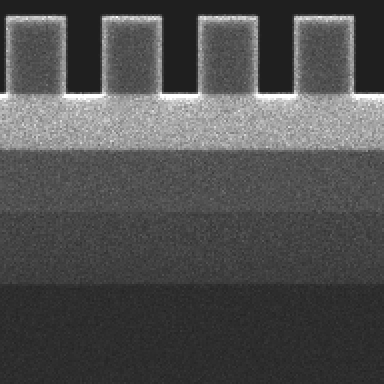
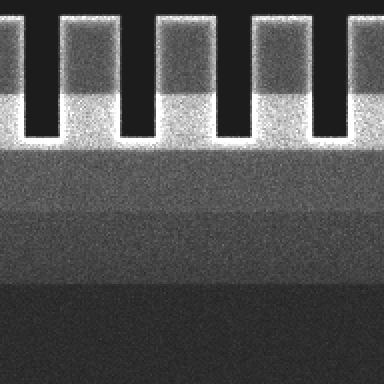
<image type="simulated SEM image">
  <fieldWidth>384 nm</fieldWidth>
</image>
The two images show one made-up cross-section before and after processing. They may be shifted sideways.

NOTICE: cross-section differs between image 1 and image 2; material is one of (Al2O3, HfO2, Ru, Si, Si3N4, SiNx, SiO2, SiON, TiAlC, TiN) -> removed: HfO2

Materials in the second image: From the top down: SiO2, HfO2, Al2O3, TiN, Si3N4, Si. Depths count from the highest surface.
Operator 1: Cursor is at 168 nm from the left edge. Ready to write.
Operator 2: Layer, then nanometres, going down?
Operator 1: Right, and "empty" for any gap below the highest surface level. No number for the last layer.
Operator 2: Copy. SiO2 78, HfO2 56, Al2O3 62, TiN 52, Si3N4 20, Si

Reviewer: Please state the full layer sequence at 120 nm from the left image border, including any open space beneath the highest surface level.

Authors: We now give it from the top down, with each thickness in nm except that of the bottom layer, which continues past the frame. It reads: empty 122, HfO2 12, Al2O3 62, TiN 52, Si3N4 20, Si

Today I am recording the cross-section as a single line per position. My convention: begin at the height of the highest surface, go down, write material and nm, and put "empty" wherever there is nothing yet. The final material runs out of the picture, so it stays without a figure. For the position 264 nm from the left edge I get SiO2 78, HfO2 56, Al2O3 62, TiN 52, Si3N4 20, Si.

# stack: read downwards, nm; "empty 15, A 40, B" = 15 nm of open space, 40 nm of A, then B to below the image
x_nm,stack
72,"SiO2 78, HfO2 56, Al2O3 62, TiN 52, Si3N4 20, Si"